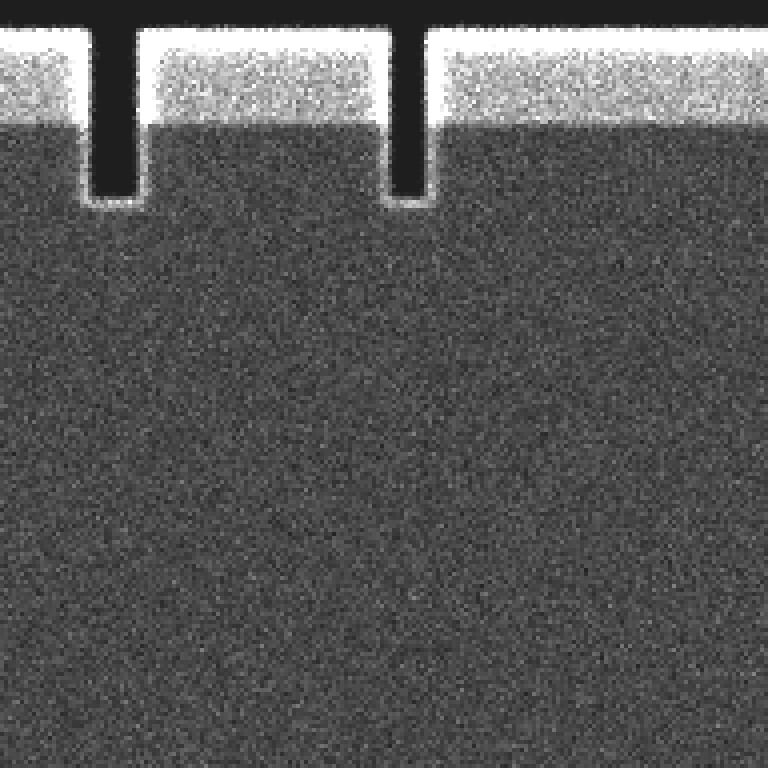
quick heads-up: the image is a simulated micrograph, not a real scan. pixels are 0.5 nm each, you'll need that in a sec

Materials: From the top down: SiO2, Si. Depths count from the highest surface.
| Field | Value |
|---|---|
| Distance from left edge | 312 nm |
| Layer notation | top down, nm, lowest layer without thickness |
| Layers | SiO2 46, Si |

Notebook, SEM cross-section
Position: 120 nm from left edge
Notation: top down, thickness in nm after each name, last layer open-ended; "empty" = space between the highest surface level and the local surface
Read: SiO2 46, Si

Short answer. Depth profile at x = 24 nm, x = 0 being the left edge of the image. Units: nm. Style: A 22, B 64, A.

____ SiO2 46, Si